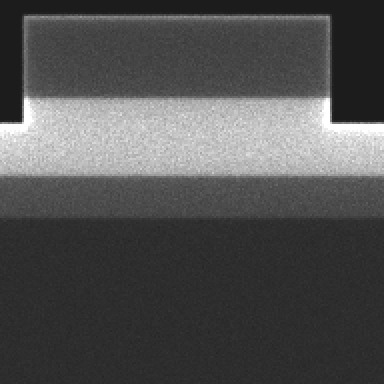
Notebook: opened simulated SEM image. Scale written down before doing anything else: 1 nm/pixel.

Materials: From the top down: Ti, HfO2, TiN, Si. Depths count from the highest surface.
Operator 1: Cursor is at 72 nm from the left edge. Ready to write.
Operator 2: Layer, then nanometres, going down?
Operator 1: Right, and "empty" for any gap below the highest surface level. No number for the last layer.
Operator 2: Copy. Ti 82, HfO2 78, TiN 42, Si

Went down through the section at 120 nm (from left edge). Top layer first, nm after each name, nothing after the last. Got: Ti 82, HfO2 78, TiN 42, Si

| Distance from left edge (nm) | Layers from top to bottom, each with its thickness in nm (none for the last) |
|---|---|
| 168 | Ti 82, HfO2 78, TiN 42, Si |